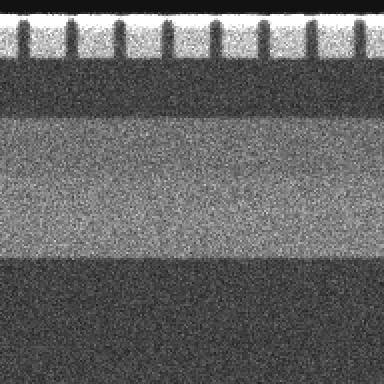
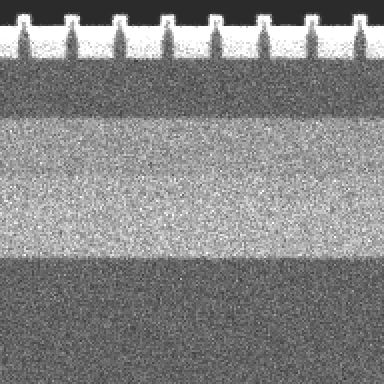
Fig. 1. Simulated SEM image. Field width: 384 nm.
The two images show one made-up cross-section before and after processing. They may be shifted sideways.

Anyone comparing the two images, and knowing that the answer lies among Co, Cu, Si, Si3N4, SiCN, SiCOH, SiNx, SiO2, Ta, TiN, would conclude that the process removed SiO2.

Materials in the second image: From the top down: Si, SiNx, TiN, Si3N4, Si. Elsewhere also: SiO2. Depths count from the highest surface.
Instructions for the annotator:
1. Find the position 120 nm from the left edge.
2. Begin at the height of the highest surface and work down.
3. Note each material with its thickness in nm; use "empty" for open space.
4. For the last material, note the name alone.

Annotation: Si 102, SiNx 58, TiN 24, Si3N4 58, Si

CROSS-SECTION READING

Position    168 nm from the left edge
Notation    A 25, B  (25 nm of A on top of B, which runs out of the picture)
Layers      Si 102, SiNx 58, TiN 24, Si3N4 58, Si